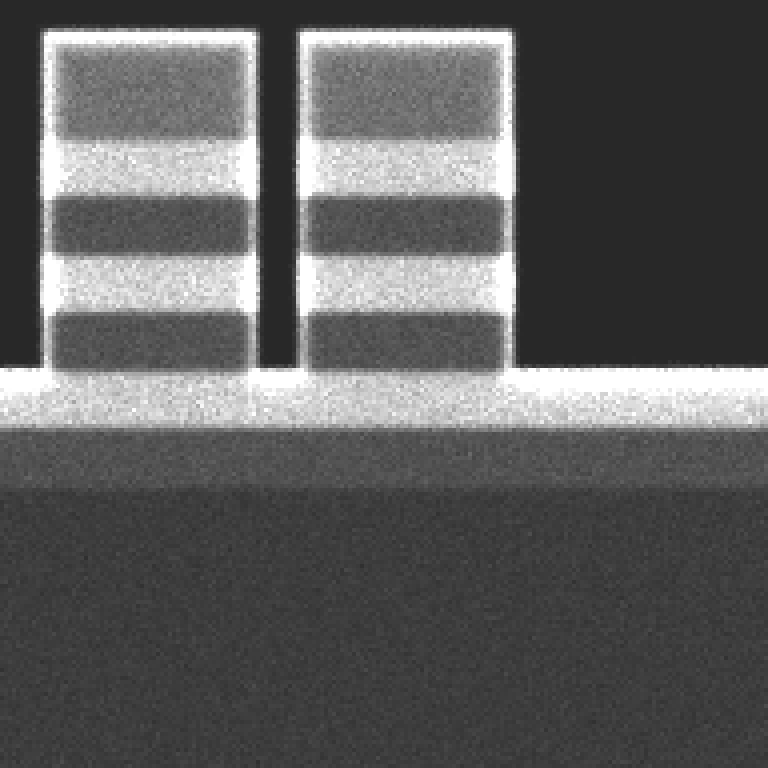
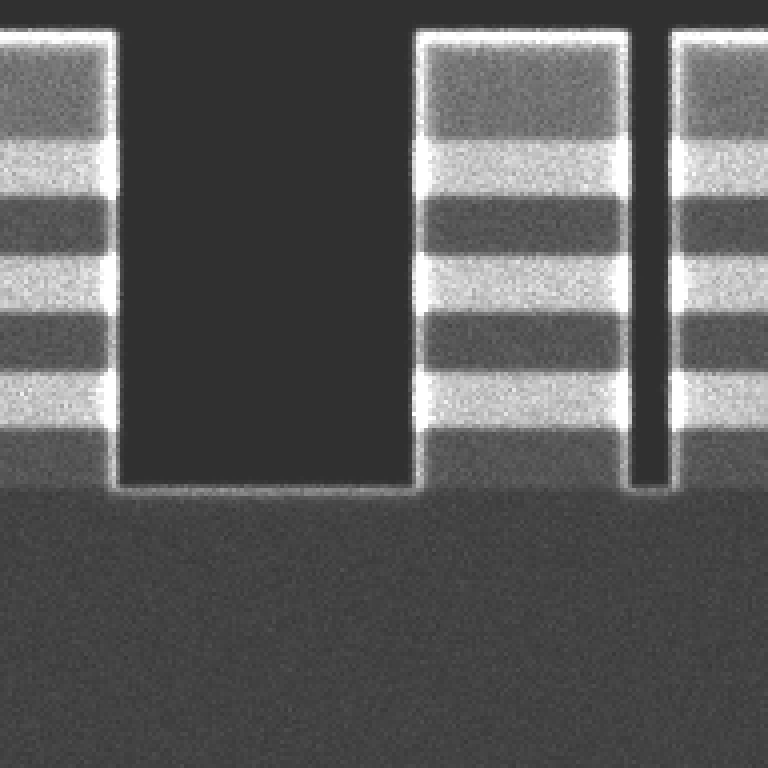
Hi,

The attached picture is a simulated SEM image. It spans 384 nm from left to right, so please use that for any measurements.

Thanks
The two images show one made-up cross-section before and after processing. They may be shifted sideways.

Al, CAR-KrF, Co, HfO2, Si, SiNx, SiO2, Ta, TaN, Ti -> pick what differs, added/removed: HfO2 and SiNx removed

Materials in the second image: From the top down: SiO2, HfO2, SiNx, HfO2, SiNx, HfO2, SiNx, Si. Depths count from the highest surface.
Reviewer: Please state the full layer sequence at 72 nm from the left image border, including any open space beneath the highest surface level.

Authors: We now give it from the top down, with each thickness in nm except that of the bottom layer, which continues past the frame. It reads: empty 228, Si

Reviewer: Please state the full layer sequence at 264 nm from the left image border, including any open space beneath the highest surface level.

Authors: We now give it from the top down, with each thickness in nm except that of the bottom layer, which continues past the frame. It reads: SiO2 54, HfO2 28, SiNx 30, HfO2 28, SiNx 30, HfO2 28, SiNx 30, Si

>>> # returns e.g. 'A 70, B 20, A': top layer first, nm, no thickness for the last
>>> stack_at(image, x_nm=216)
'SiO2 54, HfO2 28, SiNx 30, HfO2 28, SiNx 30, HfO2 28, SiNx 30, Si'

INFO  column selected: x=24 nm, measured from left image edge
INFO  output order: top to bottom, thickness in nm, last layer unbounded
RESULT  SiO2 54, HfO2 28, SiNx 30, HfO2 28, SiNx 30, HfO2 28, SiNx 30, Si